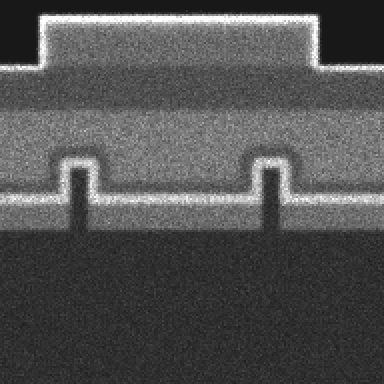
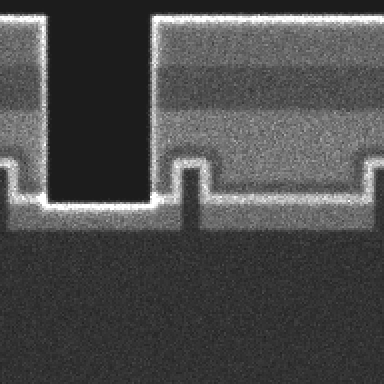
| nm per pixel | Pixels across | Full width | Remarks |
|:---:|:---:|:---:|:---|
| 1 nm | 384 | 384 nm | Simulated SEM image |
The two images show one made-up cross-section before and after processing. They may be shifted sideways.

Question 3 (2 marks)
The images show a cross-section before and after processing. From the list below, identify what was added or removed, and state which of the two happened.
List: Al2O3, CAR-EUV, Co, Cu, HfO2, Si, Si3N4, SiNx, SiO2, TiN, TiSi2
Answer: Co and HfO2 and Si3N4 and TiN was removed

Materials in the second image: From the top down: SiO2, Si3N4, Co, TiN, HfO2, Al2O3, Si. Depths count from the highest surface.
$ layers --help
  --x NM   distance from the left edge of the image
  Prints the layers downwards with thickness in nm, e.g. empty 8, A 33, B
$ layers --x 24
SiO2 50, Si3N4 44, Co 42, TiN 42, HfO2 10, Al2O3 26, Si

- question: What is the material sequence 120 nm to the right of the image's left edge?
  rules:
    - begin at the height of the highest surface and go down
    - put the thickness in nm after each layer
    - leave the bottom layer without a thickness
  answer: empty 188, Al2O3 26, Si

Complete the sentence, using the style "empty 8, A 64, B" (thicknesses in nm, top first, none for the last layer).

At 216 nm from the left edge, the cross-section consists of SiO2 50, Si3N4 44, Co 42, TiN 42, HfO2 10, Al2O3 26, Si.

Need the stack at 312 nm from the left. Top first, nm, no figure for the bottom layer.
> SiO2 50, Si3N4 44, Co 72, TiN 12, HfO2 10, Al2O3 26, Si